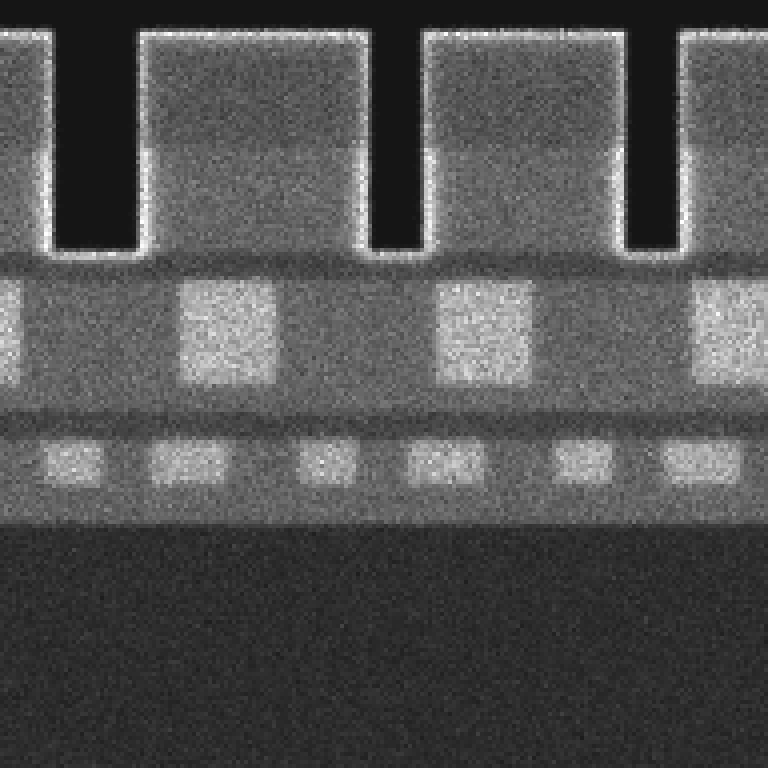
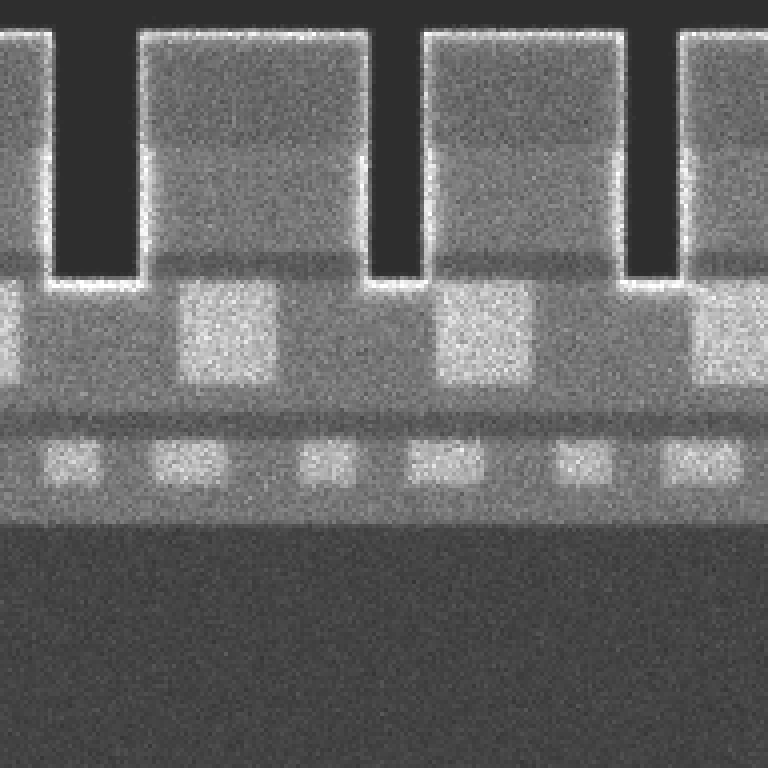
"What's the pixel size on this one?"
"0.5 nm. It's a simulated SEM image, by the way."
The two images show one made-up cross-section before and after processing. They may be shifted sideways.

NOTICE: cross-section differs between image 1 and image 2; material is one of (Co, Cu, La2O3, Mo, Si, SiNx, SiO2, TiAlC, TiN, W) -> removed: SiNx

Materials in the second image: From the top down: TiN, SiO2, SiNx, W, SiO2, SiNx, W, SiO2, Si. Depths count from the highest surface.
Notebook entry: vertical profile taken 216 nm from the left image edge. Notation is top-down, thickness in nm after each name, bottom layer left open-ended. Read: TiN 58, SiO2 52, SiNx 14, SiO2 66, SiNx 14, W 22, SiO2 20, Si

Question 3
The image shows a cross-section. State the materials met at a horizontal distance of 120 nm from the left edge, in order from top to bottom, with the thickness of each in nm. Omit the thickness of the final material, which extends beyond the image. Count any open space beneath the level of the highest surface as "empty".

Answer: TiN 58, SiO2 52, SiNx 14, W 52, SiO2 14, SiNx 14, SiO2 42, Si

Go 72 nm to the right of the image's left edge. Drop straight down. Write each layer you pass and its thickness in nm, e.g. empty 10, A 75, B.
TiN 58, SiO2 52, SiNx 14, SiO2 66, SiNx 14, SiO2 42, Si